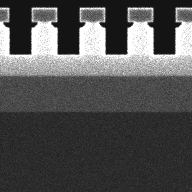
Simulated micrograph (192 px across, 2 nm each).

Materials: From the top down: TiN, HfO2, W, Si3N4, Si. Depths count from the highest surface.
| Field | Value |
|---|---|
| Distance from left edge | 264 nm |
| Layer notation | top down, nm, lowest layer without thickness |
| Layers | TiN 28, empty 8, HfO2 58, W 42, Si3N4 72, Si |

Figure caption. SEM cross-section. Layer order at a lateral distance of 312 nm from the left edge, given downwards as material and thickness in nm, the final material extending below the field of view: empty 94, W 42, Si3N4 72, Si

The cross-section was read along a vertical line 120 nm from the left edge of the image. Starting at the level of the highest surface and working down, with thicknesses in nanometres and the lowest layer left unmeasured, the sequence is empty 94, W 42, Si3N4 72, Si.